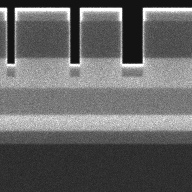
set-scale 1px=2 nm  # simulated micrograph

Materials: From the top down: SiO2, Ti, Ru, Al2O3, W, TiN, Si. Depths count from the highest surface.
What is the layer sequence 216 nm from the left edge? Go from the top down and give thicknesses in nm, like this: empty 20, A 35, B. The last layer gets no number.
SiO2 26, Ti 74, Ru 60, Al2O3 54, W 32, TiN 26, Si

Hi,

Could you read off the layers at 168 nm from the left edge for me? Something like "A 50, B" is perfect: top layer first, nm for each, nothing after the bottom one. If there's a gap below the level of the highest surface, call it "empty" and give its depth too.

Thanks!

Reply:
SiO2 26, Ti 74, Ru 60, Al2O3 54, W 32, TiN 26, Si